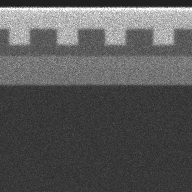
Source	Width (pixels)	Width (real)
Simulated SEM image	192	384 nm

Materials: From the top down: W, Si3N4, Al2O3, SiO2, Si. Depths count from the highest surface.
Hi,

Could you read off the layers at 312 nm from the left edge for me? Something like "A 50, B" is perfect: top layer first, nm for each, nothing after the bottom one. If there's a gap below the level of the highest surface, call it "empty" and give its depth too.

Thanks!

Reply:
W 74, Si3N4 22, Al2O3 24, SiO2 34, Si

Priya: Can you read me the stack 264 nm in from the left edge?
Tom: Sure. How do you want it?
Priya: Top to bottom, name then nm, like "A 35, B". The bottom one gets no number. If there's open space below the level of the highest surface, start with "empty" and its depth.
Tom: W 42, Si3N4 54, Al2O3 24, SiO2 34, Si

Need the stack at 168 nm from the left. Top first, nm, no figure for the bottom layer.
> W 42, Si3N4 54, Al2O3 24, SiO2 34, Si